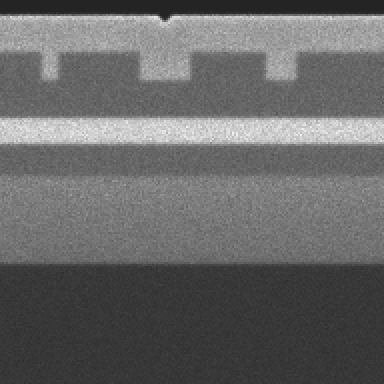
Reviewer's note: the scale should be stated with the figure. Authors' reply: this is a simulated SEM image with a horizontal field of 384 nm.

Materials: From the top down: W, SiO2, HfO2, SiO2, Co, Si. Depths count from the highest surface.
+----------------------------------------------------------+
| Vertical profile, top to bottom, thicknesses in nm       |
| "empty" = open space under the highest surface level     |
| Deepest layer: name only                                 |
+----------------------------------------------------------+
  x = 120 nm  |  W 36, SiO2 66, HfO2 26, SiO2 32, Co 88, Si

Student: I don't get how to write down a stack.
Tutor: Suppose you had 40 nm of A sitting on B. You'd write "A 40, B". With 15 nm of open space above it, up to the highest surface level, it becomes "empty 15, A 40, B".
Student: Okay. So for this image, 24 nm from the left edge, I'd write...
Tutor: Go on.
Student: W 36, SiO2 66, HfO2 26, SiO2 32, Co 88, Si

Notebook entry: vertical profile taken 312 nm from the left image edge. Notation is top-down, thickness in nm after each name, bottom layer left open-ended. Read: W 36, SiO2 66, HfO2 26, SiO2 32, Co 88, Si